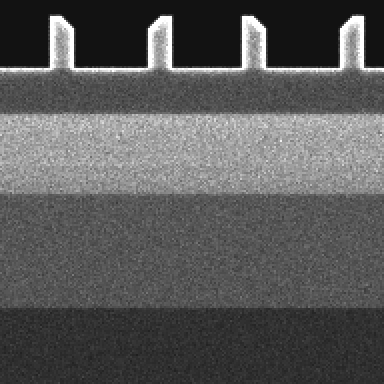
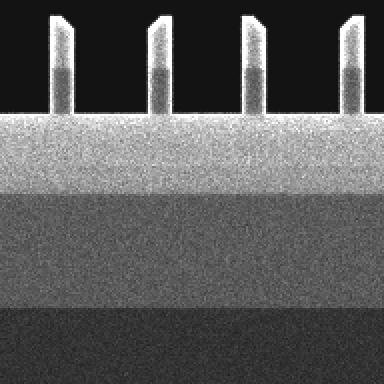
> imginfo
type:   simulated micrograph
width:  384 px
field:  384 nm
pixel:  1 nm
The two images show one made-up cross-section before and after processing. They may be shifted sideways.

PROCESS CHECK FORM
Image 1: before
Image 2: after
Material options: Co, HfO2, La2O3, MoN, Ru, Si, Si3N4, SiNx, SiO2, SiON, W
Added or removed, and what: removed, SiNx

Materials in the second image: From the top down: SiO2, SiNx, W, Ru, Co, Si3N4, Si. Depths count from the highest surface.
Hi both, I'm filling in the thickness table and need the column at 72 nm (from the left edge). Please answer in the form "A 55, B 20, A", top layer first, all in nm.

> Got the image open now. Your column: empty 12, SiO2 40, SiNx 46, W 52, Ru 14, Co 14, Si3N4 114, Si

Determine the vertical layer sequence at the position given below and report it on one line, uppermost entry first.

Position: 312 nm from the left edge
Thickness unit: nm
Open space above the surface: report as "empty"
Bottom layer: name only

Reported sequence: empty 98, W 52, Ru 14, Co 14, Si3N4 114, Si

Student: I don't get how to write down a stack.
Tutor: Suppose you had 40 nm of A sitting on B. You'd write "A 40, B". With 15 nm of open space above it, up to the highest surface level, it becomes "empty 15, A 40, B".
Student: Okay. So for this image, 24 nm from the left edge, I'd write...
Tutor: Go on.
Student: empty 98, W 52, Ru 14, Co 14, Si3N4 114, Si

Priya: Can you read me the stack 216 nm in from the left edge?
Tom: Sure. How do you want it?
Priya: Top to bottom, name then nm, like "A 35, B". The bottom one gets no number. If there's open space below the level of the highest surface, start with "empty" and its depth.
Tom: empty 98, W 52, Ru 14, Co 14, Si3N4 114, Si